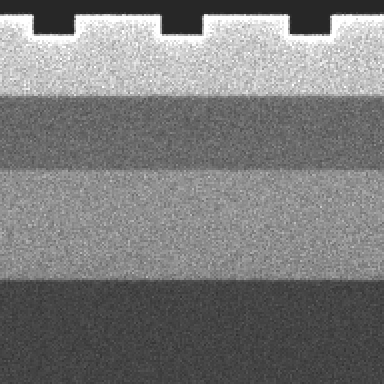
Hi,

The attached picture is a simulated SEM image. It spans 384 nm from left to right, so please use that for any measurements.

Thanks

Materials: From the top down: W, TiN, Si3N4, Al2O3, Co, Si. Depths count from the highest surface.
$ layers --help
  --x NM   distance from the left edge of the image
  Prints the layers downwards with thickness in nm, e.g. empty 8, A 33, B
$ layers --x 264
W 80, TiN 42, Si3N4 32, Al2O3 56, Co 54, Si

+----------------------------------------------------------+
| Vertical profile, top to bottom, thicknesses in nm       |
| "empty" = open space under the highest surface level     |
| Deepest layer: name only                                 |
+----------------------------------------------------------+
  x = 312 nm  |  empty 20, W 60, TiN 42, Si3N4 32, Al2O3 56, Co 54, Si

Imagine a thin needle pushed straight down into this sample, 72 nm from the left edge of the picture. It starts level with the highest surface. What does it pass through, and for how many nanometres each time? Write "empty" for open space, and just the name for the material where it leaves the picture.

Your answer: empty 20, W 60, TiN 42, Si3N4 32, Al2O3 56, Co 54, Si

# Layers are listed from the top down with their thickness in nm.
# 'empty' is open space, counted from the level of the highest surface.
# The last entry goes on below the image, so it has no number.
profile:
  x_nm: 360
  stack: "W 80, TiN 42, Si3N4 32, Al2O3 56, Co 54, Si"